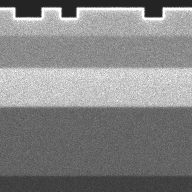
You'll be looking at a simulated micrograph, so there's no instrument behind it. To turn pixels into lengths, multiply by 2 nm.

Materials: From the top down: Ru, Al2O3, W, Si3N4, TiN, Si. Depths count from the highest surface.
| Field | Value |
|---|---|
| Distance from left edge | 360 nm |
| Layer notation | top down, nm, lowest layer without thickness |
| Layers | Ru 56, Al2O3 64, W 78, Si3N4 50, TiN 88, Si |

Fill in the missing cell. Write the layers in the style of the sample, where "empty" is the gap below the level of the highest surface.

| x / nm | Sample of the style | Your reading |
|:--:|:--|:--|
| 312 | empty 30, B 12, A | empty 20, Ru 36, Al2O3 64, W 78, Si3N4 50, TiN 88, Si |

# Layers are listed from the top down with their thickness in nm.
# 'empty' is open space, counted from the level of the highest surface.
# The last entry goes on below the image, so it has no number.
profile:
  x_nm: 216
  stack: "Ru 56, Al2O3 64, W 78, Si3N4 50, TiN 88, Si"